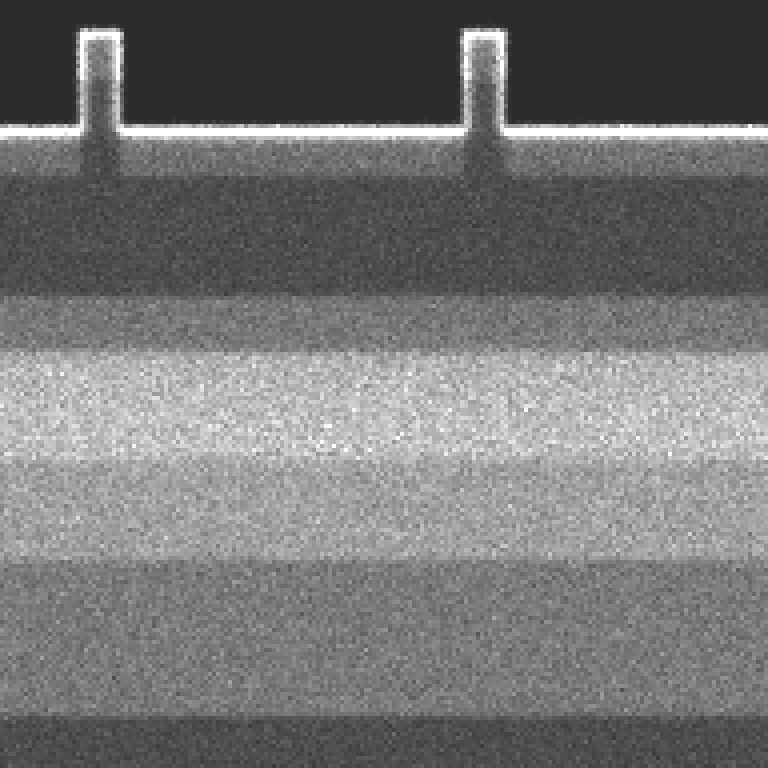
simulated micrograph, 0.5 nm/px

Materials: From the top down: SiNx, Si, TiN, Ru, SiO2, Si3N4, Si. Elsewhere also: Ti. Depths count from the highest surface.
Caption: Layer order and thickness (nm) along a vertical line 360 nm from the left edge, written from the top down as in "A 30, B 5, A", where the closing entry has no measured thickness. empty 48, SiNx 24, Si 60, TiN 28, Ru 54, SiO2 50, Si3N4 78, Si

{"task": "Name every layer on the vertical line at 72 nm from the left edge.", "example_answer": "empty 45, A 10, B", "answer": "empty 48, SiNx 24, Si 60, TiN 28, Ru 54, SiO2 50, Si3N4 78, Si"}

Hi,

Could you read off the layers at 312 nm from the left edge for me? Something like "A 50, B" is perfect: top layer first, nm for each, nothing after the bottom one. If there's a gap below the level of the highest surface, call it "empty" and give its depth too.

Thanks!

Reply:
empty 48, SiNx 24, Si 60, TiN 28, Ru 54, SiO2 50, Si3N4 78, Si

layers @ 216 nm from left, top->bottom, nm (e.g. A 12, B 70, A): empty 48, SiNx 24, Si 60, TiN 28, Ru 54, SiO2 50, Si3N4 78, Si